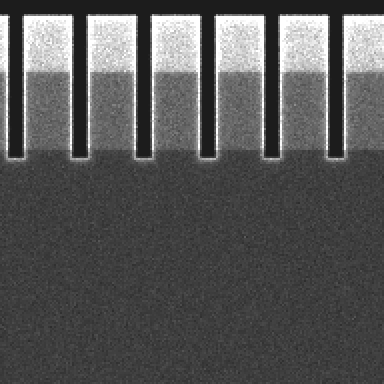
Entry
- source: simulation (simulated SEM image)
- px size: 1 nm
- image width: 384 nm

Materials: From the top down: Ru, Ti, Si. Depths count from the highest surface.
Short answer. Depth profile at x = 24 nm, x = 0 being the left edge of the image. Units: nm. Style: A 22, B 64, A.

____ Ru 56, Ti 78, Si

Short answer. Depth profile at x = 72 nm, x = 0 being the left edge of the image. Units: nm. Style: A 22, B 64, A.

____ empty 142, Si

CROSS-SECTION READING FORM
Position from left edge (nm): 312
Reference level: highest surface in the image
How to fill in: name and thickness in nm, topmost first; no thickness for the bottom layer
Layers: Ru 56, Ti 78, Si